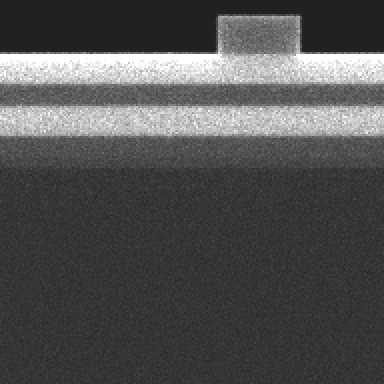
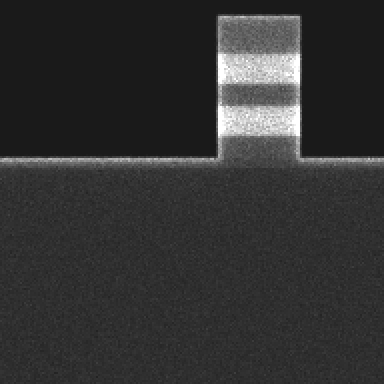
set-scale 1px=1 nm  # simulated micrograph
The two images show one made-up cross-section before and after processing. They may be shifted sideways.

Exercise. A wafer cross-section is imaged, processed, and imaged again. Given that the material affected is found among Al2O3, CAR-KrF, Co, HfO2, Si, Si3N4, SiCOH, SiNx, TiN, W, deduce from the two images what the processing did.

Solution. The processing removed HfO2 and Si3N4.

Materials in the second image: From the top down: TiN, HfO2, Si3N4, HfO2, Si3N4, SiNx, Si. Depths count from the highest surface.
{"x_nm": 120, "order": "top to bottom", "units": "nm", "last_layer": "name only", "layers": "empty 142, SiNx 10, Si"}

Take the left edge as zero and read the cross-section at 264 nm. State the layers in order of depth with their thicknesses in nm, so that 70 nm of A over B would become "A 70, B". TiN 38, HfO2 30, Si3N4 22, HfO2 30, Si3N4 22, SiNx 10, Si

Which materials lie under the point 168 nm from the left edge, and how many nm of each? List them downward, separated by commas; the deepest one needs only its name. empty 142, SiNx 10, Si